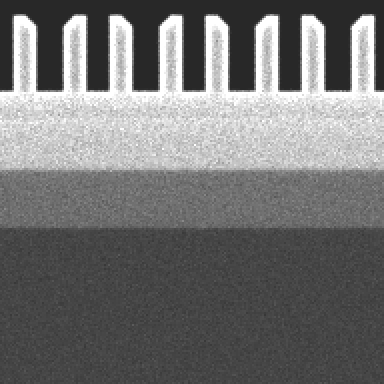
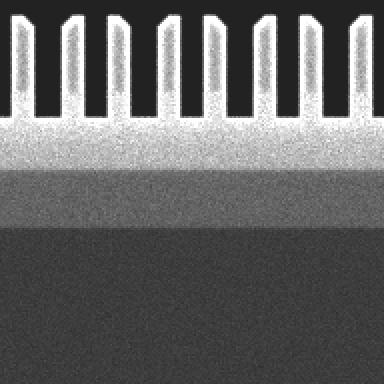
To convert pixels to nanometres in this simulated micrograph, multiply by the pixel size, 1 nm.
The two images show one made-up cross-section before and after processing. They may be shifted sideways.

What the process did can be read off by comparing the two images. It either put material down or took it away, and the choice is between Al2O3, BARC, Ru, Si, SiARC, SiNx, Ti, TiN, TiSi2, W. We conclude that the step removed Ru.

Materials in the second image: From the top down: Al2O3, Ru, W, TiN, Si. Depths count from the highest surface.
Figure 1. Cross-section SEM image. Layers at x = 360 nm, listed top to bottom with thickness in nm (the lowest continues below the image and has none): Al2O3 76, Ru 26, W 52, TiN 58, Si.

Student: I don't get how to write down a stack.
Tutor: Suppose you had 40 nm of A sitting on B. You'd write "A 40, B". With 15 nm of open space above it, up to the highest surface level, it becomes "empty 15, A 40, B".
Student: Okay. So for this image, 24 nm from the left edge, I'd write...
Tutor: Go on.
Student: empty 2, Al2O3 74, Ru 26, W 52, TiN 58, Si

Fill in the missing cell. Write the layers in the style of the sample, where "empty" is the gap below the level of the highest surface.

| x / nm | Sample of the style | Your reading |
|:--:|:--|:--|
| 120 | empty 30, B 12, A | empty 2, Al2O3 74, Ru 26, W 52, TiN 58, Si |